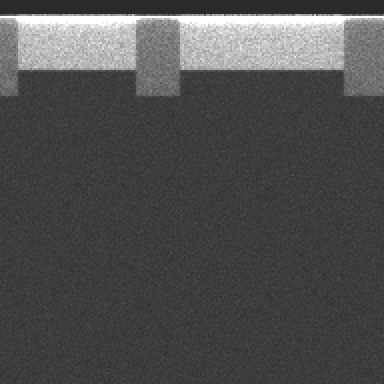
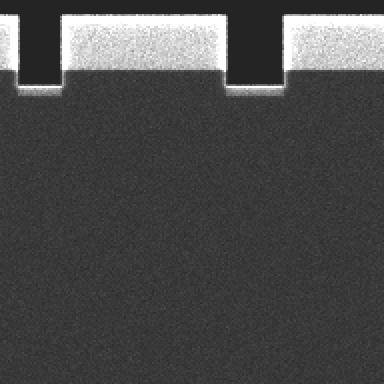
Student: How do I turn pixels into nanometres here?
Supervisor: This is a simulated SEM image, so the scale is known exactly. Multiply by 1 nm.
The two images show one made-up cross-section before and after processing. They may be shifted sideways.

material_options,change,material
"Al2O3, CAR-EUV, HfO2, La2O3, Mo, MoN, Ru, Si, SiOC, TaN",removed,Ru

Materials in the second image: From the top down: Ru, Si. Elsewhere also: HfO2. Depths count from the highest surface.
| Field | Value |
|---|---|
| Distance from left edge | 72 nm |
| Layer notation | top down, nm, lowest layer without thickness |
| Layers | HfO2 54, Si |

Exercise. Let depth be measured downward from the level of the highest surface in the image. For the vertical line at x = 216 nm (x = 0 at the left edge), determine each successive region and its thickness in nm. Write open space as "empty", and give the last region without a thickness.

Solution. HfO2 54, Si